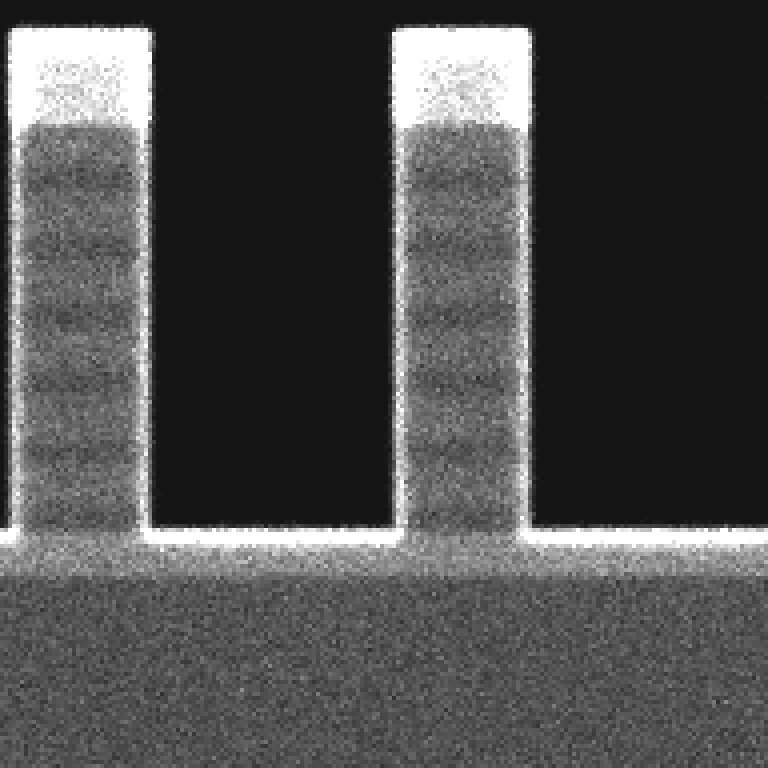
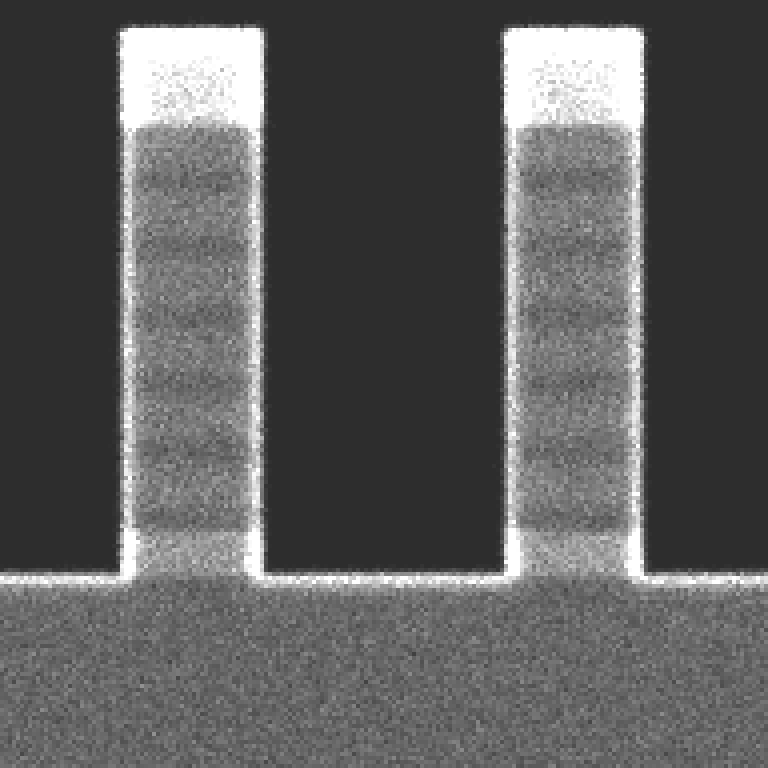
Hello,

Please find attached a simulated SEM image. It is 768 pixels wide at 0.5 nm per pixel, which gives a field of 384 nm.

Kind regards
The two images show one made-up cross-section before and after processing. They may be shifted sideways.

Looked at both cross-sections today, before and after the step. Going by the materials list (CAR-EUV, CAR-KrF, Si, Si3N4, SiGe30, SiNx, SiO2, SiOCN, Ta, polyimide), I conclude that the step removed SiNx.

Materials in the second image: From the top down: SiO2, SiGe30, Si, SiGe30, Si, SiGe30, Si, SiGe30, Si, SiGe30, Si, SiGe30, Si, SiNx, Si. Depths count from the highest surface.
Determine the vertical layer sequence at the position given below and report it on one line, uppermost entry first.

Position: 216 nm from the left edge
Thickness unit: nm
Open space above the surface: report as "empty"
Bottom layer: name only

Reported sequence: empty 272, Si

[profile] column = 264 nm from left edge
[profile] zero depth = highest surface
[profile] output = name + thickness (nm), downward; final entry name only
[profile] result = SiO2 46, SiGe30 22, Si 12, SiGe30 22, Si 12, SiGe30 22, Si 12, SiGe30 22, Si 12, SiGe30 22, Si 12, SiGe30 22, Si 12, SiNx 22, Si